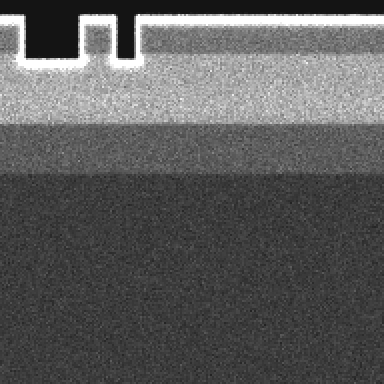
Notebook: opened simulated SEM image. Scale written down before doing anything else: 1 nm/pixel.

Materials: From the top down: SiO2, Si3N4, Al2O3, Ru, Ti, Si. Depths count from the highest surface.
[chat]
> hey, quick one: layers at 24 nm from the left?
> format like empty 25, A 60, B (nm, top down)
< empty 44, Al2O3 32, Ru 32, Ti 50, Si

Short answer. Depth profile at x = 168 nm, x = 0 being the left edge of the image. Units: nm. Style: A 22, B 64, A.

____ SiO2 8, Si3N4 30, Al2O3 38, Ru 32, Ti 50, Si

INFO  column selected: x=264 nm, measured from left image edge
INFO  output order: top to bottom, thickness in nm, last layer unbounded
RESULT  SiO2 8, Si3N4 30, Al2O3 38, Ru 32, Ti 50, Si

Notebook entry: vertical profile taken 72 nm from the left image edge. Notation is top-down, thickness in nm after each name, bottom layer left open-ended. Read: empty 44, Al2O3 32, Ru 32, Ti 50, Si